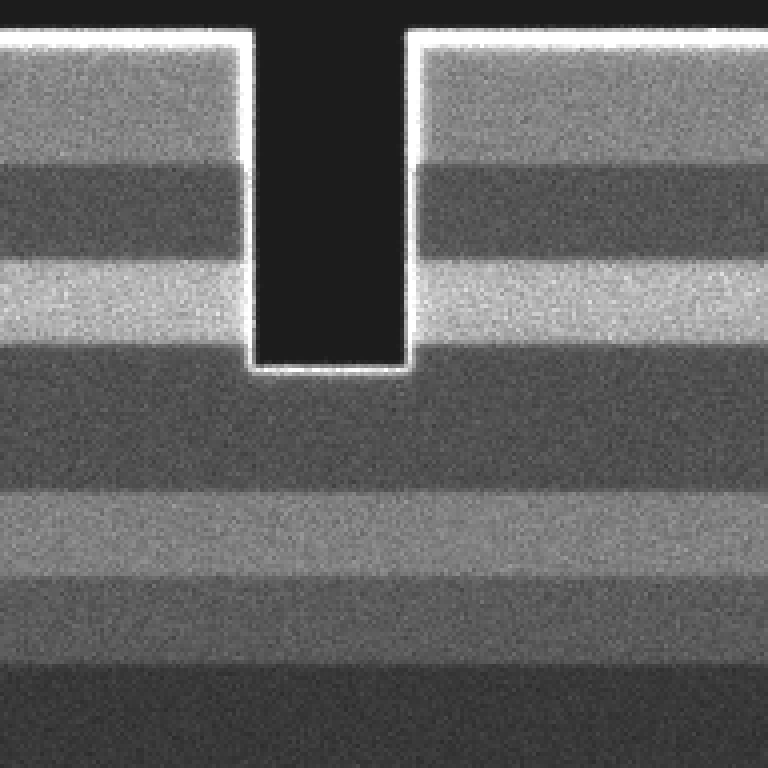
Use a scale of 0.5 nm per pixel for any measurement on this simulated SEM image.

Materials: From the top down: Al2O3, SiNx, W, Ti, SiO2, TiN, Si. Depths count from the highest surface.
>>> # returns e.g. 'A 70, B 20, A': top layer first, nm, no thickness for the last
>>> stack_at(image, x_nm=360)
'Al2O3 66, SiNx 48, W 42, Ti 74, SiO2 42, TiN 44, Si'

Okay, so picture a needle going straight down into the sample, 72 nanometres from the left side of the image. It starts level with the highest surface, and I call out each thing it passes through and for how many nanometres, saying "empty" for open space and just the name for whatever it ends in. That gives Al2O3 66, SiNx 48, W 42, Ti 74, SiO2 42, TiN 44, Si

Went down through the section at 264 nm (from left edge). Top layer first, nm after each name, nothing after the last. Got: Al2O3 66, SiNx 48, W 42, Ti 74, SiO2 42, TiN 44, Si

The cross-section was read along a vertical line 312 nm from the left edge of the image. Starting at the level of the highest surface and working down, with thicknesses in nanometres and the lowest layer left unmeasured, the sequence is Al2O3 66, SiNx 48, W 42, Ti 74, SiO2 42, TiN 44, Si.